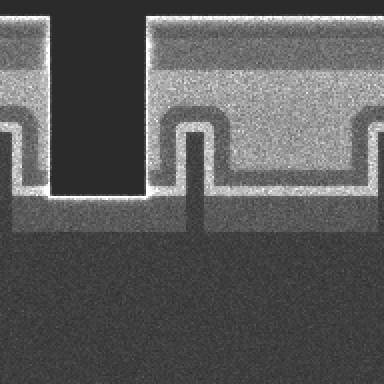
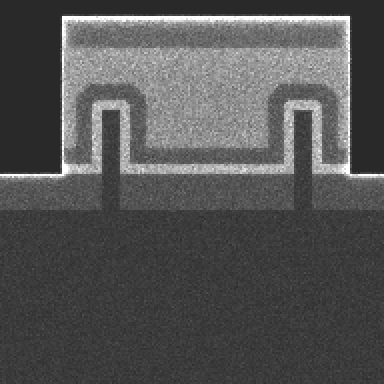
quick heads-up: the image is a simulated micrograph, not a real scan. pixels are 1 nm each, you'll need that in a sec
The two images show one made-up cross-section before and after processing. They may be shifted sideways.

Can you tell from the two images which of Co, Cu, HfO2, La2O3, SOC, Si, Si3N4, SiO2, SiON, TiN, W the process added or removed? Yes, it removed SOC.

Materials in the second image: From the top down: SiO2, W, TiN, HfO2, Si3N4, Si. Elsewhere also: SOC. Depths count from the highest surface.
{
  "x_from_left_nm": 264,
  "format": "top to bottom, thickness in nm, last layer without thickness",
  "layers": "SiO2 32, W 100, TiN 16, HfO2 10, Si3N4 36, Si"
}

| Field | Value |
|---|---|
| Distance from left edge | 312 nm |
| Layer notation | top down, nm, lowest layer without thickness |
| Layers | SiO2 32, W 36, TiN 16, HfO2 74, Si3N4 36, Si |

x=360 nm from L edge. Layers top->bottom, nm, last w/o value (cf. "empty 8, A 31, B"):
empty 158, Si3N4 36, Si